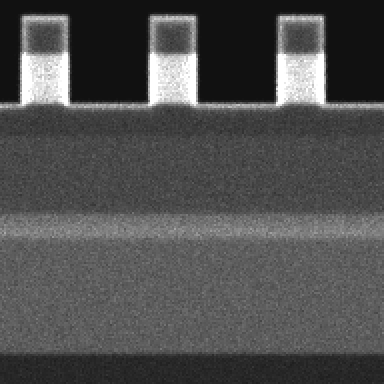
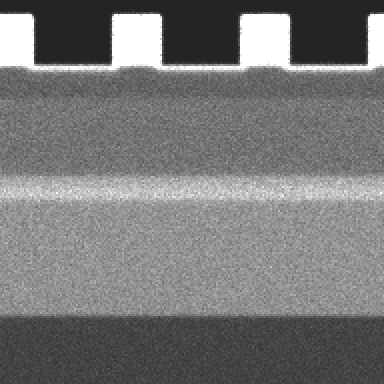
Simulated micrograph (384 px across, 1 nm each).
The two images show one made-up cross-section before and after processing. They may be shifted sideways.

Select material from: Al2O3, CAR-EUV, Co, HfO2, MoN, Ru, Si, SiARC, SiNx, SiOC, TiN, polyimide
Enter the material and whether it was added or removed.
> SiARC / removed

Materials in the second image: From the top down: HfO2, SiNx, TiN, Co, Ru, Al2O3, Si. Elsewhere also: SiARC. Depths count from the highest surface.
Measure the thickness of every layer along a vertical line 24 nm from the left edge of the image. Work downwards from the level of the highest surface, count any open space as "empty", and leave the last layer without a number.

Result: HfO2 50, SiNx 32, TiN 78, Co 12, Ru 12, Al2O3 116, Si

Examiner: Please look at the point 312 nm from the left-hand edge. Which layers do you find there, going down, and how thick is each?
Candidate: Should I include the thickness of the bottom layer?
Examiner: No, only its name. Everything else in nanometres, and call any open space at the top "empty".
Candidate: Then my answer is empty 50, SiNx 32, TiN 78, Co 12, Ru 12, Al2O3 116, Si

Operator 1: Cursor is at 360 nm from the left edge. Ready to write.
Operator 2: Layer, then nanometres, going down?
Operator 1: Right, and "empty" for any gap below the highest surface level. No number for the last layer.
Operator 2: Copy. empty 50, SiNx 32, TiN 78, Co 12, Ru 12, Al2O3 116, Si